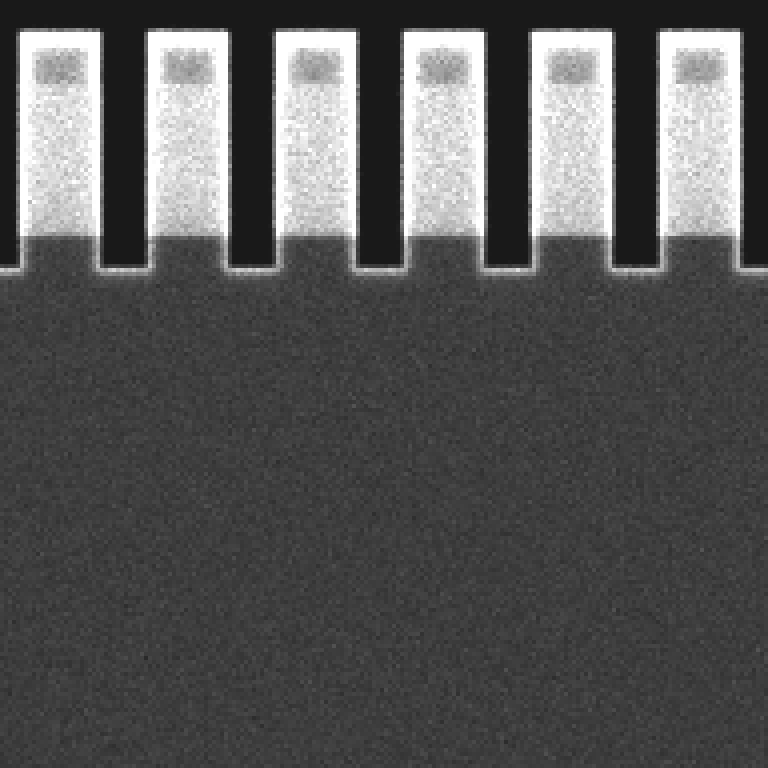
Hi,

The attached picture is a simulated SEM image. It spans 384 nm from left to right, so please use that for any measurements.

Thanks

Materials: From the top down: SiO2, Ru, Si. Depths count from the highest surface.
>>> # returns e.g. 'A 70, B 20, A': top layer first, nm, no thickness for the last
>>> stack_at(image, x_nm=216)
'SiO2 26, Ru 76, Si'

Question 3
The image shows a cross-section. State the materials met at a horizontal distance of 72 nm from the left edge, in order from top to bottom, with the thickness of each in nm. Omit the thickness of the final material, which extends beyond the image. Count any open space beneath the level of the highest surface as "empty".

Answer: empty 118, Si